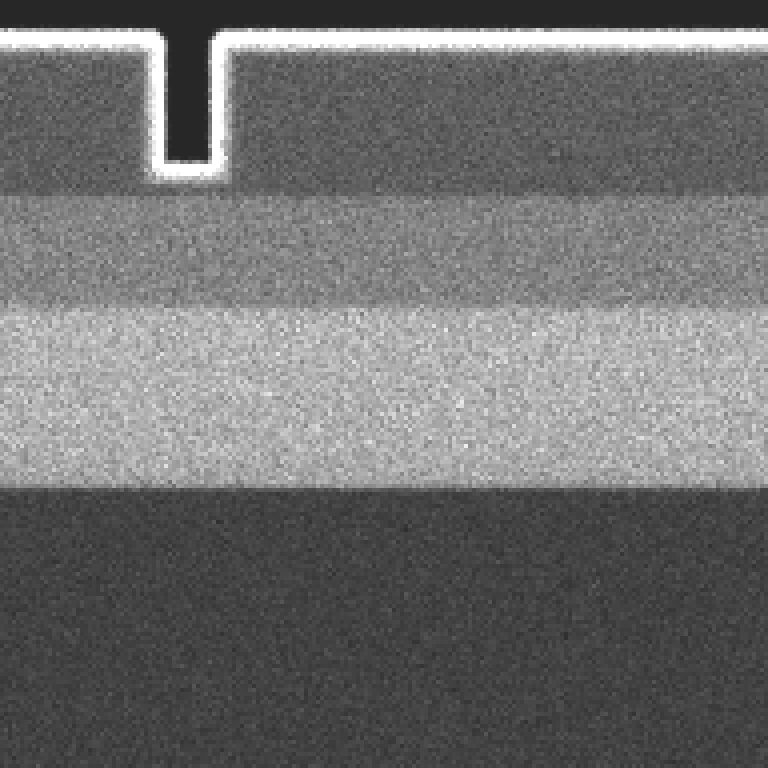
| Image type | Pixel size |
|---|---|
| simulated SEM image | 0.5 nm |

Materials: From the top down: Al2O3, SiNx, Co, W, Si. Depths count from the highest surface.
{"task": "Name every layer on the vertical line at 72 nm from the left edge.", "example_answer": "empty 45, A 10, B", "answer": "Al2O3 76, SiNx 6, Co 56, W 90, Si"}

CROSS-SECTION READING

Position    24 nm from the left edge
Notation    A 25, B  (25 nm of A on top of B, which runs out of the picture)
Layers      Al2O3 10, SiNx 72, Co 56, W 90, Si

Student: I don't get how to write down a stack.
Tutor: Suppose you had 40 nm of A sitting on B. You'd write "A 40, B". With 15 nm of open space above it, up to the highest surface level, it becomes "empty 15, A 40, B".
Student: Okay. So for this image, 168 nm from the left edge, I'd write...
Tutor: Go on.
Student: Al2O3 10, SiNx 72, Co 56, W 90, Si